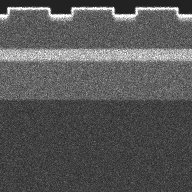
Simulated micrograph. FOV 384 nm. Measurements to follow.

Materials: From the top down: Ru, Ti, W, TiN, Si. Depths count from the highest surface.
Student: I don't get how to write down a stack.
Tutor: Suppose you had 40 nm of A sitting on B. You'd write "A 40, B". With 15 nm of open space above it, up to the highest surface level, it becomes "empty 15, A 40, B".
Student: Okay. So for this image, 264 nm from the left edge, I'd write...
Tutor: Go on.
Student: empty 14, Ru 12, Ti 56, W 24, TiN 78, Si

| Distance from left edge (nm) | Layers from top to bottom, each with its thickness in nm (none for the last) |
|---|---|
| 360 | empty 14, Ru 12, Ti 56, W 24, TiN 78, Si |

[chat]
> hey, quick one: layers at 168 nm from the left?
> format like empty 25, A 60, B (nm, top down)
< Ti 82, W 24, TiN 78, Si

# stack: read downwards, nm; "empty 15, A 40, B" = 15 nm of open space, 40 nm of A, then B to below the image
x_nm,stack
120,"empty 14, Ru 12, Ti 56, W 24, TiN 78, Si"